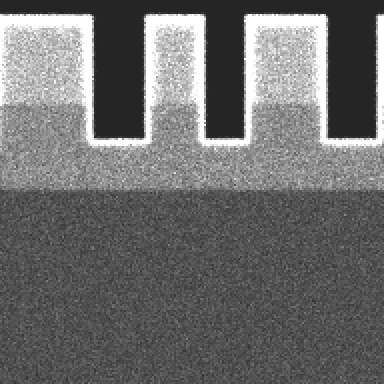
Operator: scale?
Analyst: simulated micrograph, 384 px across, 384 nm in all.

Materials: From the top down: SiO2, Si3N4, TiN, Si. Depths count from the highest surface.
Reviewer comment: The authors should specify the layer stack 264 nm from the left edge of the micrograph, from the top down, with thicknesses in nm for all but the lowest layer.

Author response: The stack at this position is SiO2 88, Si3N4 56, TiN 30, Si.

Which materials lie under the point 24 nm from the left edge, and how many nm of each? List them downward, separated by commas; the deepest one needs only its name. SiO2 88, Si3N4 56, TiN 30, Si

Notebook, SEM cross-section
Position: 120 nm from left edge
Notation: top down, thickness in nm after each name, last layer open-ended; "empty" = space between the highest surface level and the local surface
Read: empty 124, Si3N4 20, TiN 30, Si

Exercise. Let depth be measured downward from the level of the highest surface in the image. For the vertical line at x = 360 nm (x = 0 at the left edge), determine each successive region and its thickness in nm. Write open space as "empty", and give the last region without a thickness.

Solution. empty 124, Si3N4 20, TiN 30, Si